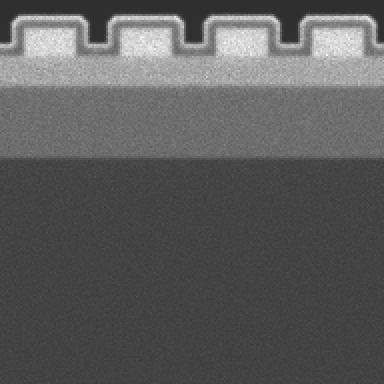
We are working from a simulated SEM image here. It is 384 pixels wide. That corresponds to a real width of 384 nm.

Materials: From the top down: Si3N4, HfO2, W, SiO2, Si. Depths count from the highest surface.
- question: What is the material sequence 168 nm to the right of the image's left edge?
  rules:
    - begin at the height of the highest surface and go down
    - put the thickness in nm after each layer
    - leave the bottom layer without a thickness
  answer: Si3N4 12, HfO2 28, W 30, SiO2 72, Si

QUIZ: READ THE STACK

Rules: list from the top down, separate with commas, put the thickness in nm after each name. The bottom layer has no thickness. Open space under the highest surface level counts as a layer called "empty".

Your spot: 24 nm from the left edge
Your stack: Si3N4 12, HfO2 28, W 30, SiO2 72, Si